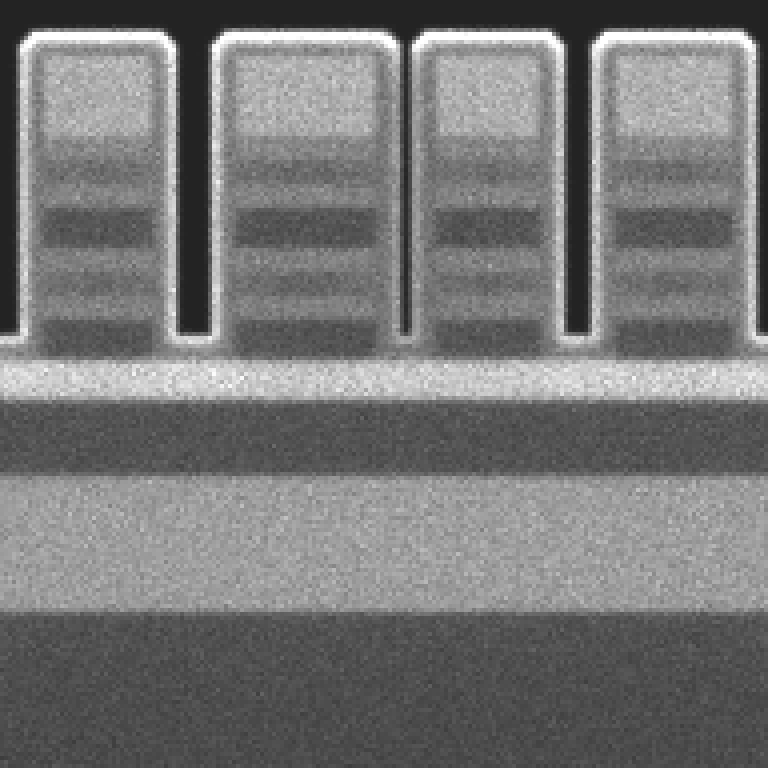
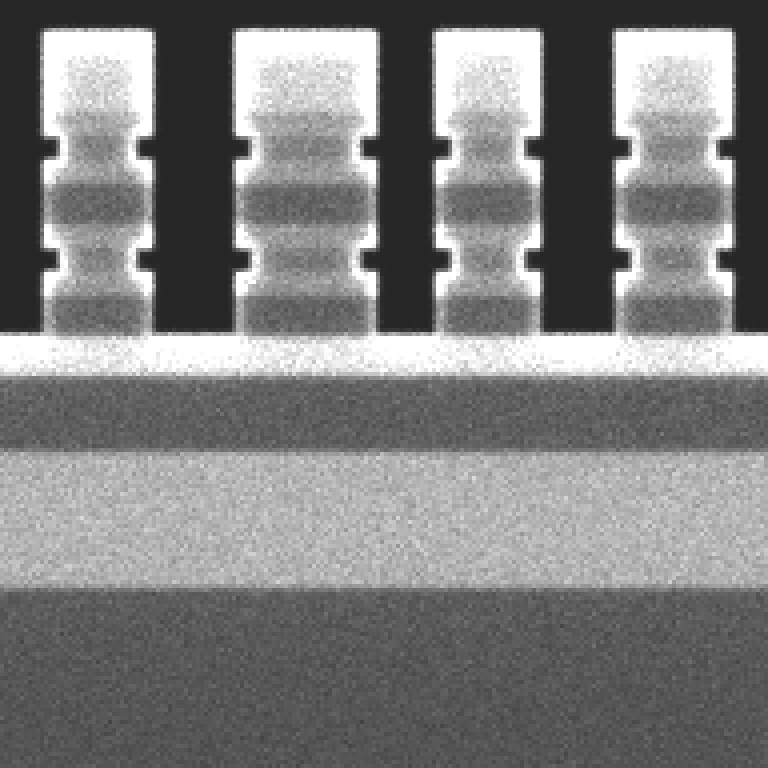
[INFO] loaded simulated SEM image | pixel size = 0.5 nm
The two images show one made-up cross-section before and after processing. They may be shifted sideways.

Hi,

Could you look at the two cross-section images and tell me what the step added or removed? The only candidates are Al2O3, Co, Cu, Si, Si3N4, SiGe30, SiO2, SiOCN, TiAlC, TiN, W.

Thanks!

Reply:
removed SiOCN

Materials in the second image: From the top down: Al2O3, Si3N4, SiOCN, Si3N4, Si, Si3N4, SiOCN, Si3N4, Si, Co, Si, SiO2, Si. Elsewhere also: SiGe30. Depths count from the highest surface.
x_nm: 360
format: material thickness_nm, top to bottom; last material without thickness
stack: Al2O3 40, Si3N4 12, empty 12, Si3N4 12, Si 20, Si3N4 12, empty 12, Si3N4 12, Si 20, Co 20, Si 38, SiO2 68, Si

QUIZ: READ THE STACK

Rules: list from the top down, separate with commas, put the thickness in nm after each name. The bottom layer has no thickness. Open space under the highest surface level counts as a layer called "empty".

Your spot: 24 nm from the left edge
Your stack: Al2O3 40, Si3N4 12, empty 12, Si3N4 12, Si 20, Si3N4 12, empty 12, Si3N4 12, Si 20, Co 20, Si 38, SiO2 68, Si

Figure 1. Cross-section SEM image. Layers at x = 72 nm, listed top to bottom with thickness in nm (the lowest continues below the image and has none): Al2O3 40, Si3N4 12, empty 12, Si3N4 12, Si 20, Si3N4 12, empty 12, Si3N4 12, Si 20, Co 20, Si 38, SiO2 68, Si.